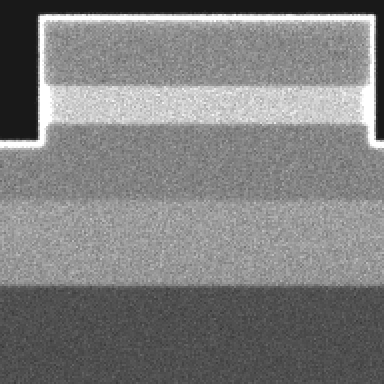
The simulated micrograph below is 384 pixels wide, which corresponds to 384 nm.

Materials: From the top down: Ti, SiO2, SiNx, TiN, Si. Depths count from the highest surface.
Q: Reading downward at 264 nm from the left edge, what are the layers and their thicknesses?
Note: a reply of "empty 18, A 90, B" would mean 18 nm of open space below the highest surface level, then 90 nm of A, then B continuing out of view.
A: Ti 70, SiO2 38, SiNx 76, TiN 86, Si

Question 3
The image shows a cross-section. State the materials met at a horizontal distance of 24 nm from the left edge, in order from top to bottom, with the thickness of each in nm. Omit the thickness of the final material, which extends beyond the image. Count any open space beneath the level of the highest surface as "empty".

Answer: empty 126, SiNx 58, TiN 86, Si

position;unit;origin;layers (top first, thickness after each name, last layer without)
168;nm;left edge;Ti 70, SiO2 38, SiNx 76, TiN 86, Si